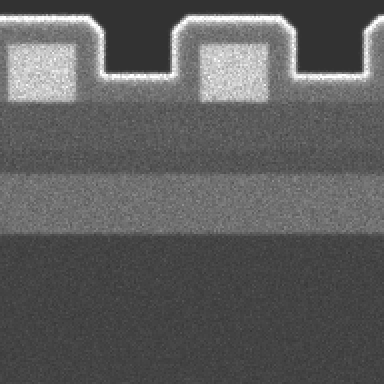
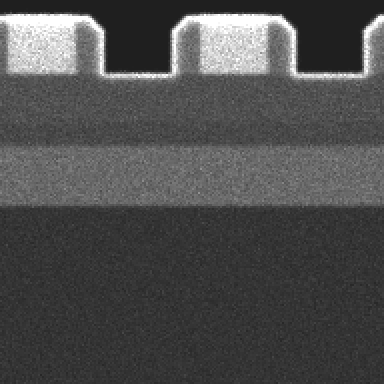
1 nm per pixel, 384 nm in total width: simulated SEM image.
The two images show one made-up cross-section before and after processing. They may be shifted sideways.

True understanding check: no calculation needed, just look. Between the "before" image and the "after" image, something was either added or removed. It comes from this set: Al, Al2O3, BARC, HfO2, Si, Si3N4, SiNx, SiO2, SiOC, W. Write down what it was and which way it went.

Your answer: SiO2 (removed)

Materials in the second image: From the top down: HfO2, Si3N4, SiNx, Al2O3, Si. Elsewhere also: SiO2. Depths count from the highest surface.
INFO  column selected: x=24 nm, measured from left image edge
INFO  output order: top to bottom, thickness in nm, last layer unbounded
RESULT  HfO2 58, Si3N4 48, SiNx 24, Al2O3 60, Si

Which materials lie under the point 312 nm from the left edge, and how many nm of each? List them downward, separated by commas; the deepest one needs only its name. empty 58, Si3N4 48, SiNx 24, Al2O3 60, Si